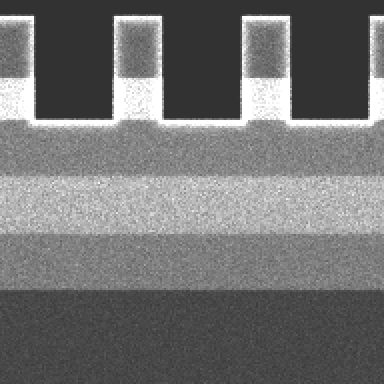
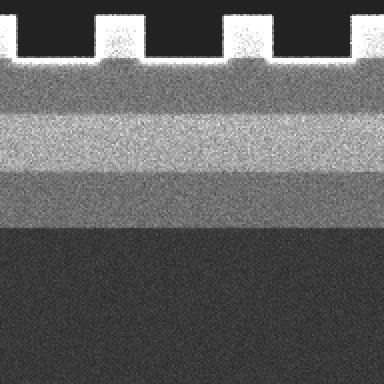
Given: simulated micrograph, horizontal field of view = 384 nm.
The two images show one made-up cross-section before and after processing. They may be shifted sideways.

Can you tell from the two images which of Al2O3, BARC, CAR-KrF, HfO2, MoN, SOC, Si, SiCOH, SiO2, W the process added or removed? Yes, it removed SOC.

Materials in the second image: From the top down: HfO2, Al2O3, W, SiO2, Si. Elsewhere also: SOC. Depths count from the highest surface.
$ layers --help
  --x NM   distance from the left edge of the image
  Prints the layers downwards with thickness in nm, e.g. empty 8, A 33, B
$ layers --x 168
empty 42, Al2O3 56, W 58, SiO2 56, Si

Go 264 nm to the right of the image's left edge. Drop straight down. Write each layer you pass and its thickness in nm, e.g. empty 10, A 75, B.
HfO2 42, Al2O3 56, W 58, SiO2 56, Si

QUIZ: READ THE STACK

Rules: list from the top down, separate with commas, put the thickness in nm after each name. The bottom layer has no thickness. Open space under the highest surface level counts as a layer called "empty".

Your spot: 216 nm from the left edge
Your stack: empty 42, Al2O3 56, W 58, SiO2 56, Si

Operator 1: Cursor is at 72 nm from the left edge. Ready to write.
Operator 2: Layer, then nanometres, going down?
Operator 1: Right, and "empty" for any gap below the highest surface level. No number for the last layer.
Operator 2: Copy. empty 42, Al2O3 56, W 58, SiO2 56, Si